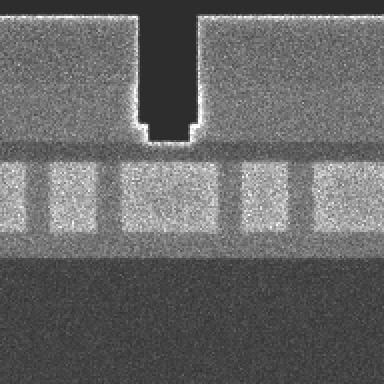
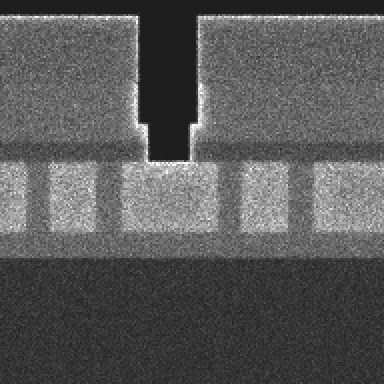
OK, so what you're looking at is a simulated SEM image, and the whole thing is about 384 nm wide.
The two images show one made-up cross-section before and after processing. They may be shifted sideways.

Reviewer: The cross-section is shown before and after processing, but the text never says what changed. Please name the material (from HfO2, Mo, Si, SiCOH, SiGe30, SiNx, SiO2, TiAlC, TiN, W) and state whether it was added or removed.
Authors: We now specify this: SiNx, removed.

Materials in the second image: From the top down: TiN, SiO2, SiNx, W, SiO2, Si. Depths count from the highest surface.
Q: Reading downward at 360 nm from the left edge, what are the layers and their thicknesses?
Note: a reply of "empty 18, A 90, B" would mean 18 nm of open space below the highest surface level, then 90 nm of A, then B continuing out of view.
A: TiN 68, SiO2 58, SiNx 20, W 70, SiO2 26, Si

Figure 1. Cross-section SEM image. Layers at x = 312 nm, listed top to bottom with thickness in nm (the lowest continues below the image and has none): TiN 68, SiO2 58, SiNx 20, SiO2 96, Si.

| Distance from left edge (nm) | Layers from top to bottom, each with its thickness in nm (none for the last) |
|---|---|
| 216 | TiN 68, SiO2 58, SiNx 20, W 70, SiO2 26, Si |